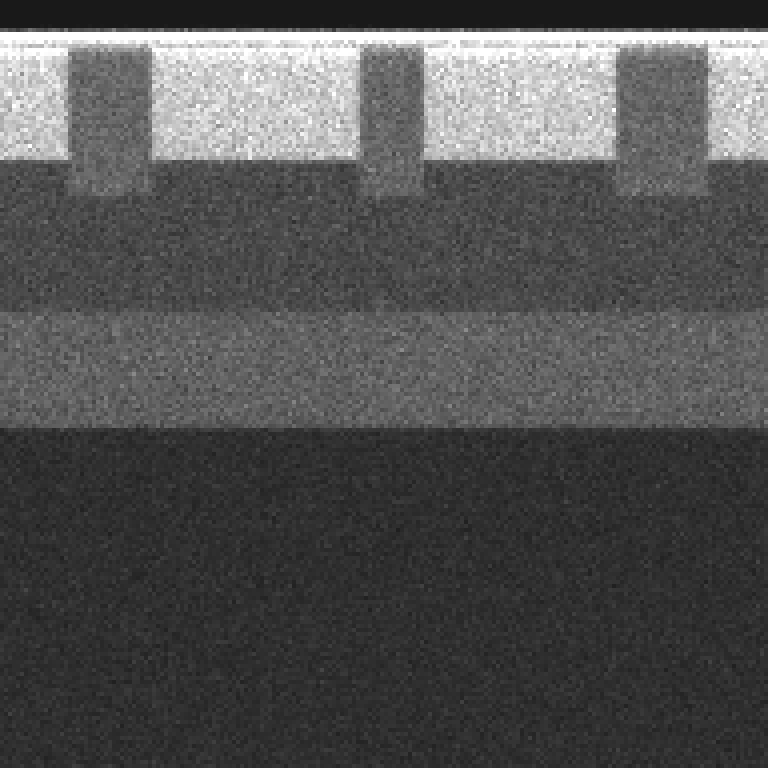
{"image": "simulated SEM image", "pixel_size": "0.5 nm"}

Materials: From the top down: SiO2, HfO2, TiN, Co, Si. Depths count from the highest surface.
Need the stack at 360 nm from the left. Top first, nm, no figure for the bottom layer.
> SiO2 8, HfO2 56, TiN 76, Co 58, Si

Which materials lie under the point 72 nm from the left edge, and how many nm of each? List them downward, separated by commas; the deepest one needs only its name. SiO2 82, TiN 58, Co 58, Si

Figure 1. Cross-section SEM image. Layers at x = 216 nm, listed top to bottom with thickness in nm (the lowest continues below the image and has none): SiO2 8, HfO2 56, TiN 76, Co 58, Si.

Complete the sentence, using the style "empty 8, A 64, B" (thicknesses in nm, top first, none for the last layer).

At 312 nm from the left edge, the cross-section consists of SiO2 82, TiN 58, Co 58, Si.